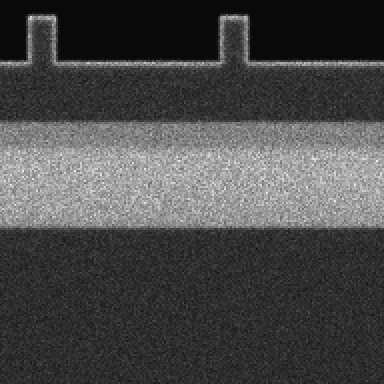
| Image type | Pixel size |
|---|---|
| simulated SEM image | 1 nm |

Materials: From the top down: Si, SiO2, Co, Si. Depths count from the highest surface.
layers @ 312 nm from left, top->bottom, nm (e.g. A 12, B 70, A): empty 46, Si 60, SiO2 26, Co 80, Si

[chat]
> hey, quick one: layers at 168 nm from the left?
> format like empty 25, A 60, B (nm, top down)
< empty 46, Si 60, SiO2 26, Co 80, Si